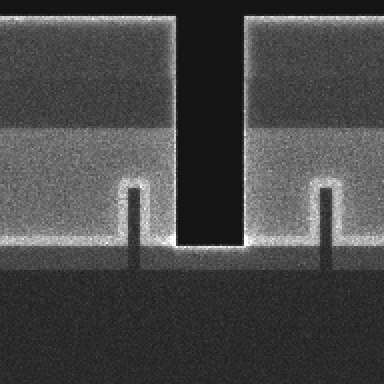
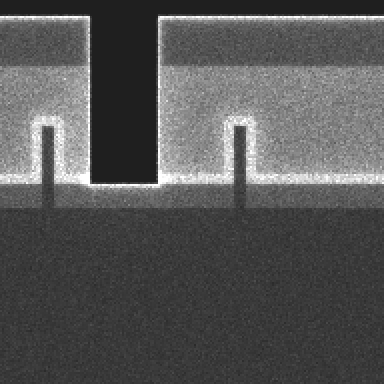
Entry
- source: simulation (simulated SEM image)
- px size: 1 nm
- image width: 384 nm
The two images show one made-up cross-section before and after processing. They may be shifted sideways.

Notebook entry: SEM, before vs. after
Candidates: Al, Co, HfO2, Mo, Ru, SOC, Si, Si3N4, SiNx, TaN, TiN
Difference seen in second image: SOC removed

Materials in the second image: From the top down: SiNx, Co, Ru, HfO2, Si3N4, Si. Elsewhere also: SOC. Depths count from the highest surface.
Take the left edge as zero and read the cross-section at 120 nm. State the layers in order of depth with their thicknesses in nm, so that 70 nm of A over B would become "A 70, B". empty 168, Si3N4 24, Si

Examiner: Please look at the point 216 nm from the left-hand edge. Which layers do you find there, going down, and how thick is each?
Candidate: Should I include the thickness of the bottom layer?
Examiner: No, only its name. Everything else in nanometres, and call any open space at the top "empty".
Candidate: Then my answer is SiNx 50, Co 46, Ru 62, HfO2 10, Si3N4 24, Si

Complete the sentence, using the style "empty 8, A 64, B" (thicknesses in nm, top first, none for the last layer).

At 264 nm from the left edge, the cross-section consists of SiNx 50, Co 48, Ru 60, HfO2 10, Si3N4 24, Si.